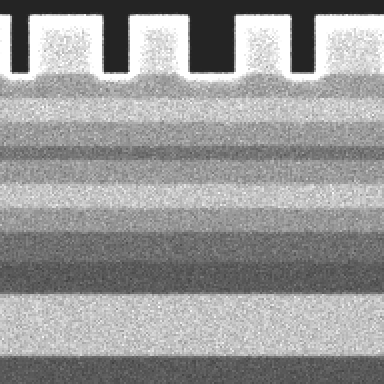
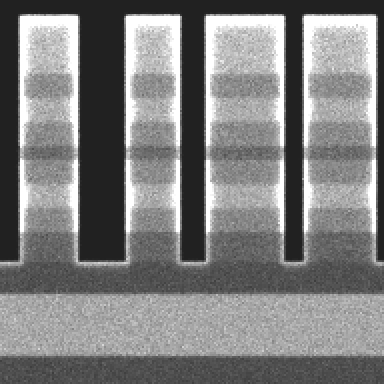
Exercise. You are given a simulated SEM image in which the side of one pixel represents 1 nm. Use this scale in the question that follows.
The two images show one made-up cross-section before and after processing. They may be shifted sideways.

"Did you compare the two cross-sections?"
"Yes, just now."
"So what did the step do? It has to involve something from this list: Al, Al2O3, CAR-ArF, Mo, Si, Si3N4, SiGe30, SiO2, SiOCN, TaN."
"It removed Si3N4 and SiGe30 and SiO2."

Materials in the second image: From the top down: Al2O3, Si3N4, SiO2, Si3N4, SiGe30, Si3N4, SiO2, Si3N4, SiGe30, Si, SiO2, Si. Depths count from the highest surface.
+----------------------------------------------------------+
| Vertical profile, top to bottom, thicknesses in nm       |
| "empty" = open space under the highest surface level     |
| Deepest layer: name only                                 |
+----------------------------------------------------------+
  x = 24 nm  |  Al2O3 58, Si3N4 24, SiO2 24, Si3N4 24, SiGe30 14, Si3N4 24, SiO2 24, Si3N4 24, SiGe30 30, Si 32, SiO2 62, Si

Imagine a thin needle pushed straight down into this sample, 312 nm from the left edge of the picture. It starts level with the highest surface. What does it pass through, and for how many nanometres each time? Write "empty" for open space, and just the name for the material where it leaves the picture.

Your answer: Al2O3 58, Si3N4 24, SiO2 24, Si3N4 24, SiGe30 14, Si3N4 24, SiO2 24, Si3N4 24, SiGe30 30, Si 32, SiO2 62, Si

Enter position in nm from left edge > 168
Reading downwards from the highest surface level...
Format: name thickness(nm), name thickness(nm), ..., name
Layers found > Al2O3 58, Si3N4 24, SiO2 24, Si3N4 24, SiGe30 14, Si3N4 24, SiO2 24, Si3N4 24, SiGe30 30, Si 32, SiO2 62, Si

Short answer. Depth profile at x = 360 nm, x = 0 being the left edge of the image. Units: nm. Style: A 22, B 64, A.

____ Al2O3 58, Si3N4 24, SiO2 24, Si3N4 24, SiGe30 14, Si3N4 24, SiO2 24, Si3N4 24, SiGe30 30, Si 32, SiO2 62, Si